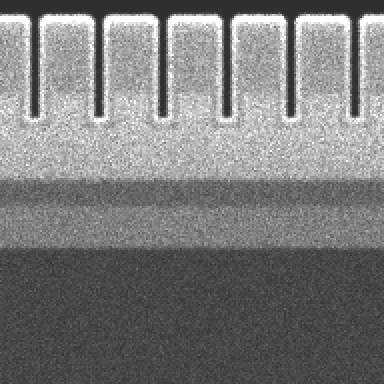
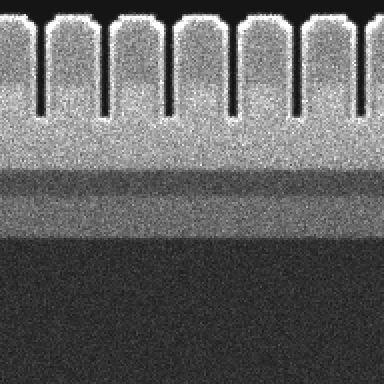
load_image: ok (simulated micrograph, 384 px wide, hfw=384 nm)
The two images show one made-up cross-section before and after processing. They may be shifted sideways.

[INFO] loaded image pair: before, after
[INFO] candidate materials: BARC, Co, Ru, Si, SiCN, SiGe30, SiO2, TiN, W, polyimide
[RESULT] removed SiO2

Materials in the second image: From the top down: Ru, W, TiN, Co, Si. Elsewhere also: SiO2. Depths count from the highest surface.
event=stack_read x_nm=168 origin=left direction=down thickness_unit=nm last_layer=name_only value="empty 102, W 52, TiN 26, Co 42, Si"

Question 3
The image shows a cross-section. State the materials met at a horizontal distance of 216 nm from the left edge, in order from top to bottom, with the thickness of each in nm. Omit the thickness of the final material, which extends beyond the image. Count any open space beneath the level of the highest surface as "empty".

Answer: Ru 68, W 86, TiN 26, Co 42, Si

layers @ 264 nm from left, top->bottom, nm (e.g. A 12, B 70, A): Ru 68, W 86, TiN 26, Co 42, Si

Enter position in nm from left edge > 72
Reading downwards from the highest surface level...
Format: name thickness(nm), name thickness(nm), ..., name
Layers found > Ru 68, W 86, TiN 26, Co 42, Si